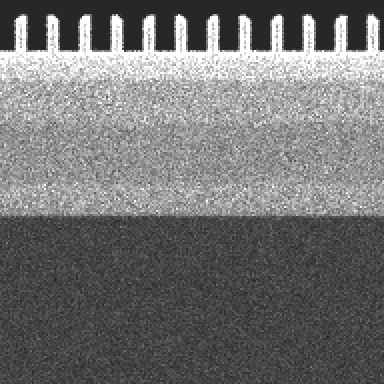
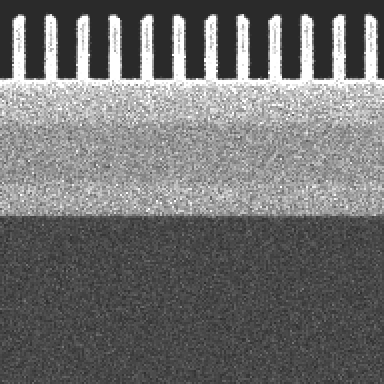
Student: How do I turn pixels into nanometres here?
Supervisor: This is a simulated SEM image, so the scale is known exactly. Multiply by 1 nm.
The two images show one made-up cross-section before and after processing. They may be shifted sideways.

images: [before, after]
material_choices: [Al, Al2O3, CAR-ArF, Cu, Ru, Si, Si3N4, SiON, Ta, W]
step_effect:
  removed: W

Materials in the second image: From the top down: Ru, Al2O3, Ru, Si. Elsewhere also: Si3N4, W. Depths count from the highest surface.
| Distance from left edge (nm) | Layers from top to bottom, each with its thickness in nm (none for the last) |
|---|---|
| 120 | empty 64, Ru 44, Al2O3 60, Ru 32, Si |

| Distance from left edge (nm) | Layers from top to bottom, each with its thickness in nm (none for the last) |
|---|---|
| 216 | empty 64, Ru 44, Al2O3 60, Ru 32, Si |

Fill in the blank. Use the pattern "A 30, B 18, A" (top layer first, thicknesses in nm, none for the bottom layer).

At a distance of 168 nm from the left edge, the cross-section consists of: empty 64, Ru 44, Al2O3 60, Ru 32, Si